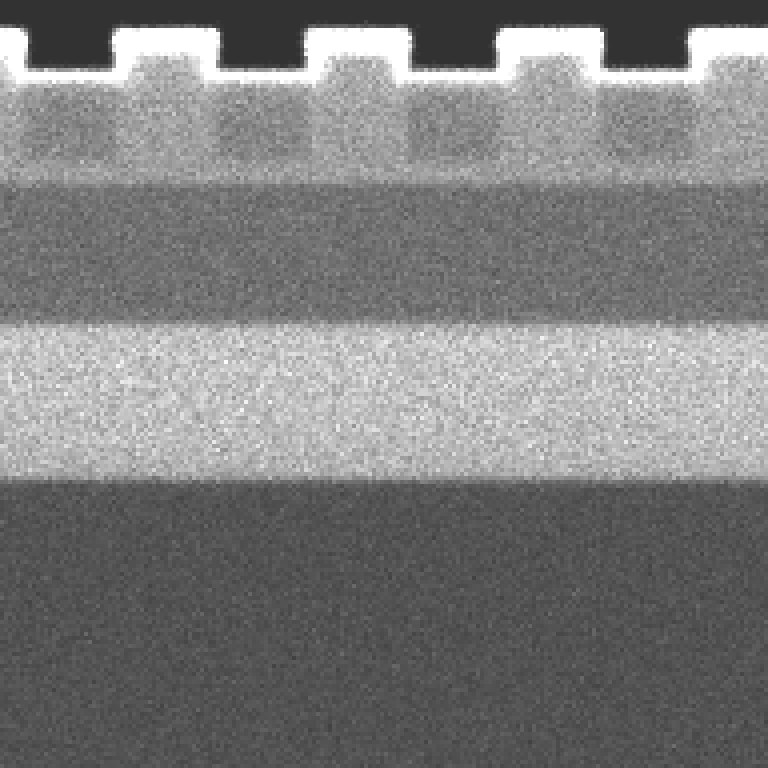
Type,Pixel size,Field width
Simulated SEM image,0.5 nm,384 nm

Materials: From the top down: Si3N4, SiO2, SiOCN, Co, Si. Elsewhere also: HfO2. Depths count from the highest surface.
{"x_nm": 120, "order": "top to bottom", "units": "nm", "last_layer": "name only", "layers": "empty 20, Si3N4 44, SiO2 12, SiOCN 70, Co 78, Si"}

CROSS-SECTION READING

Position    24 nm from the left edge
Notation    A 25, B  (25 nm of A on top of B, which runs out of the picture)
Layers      empty 20, Si3N4 44, SiO2 12, SiOCN 70, Co 78, Si